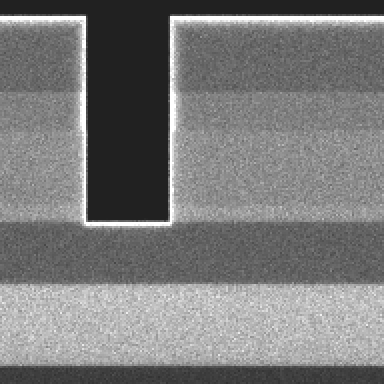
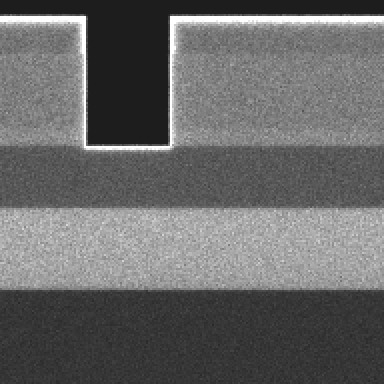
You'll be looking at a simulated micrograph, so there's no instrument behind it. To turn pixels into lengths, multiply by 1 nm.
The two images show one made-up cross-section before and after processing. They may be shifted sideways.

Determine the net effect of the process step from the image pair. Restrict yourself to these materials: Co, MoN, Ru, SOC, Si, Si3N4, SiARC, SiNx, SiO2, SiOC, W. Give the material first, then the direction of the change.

SOC: removed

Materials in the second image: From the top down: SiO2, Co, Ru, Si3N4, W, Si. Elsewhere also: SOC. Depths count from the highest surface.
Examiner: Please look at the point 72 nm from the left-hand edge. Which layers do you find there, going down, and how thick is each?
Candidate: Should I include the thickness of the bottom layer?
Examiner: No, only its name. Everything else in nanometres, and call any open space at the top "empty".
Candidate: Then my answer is SiO2 38, Co 76, Ru 16, Si3N4 62, W 82, Si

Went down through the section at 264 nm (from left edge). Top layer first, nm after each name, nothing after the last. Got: SiO2 38, Co 76, Ru 16, Si3N4 62, W 82, Si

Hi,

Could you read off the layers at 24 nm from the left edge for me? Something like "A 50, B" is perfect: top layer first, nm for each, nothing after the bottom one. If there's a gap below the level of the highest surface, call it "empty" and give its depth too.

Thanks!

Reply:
SiO2 38, Co 76, Ru 16, Si3N4 62, W 82, Si